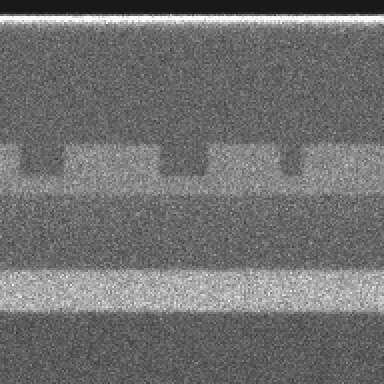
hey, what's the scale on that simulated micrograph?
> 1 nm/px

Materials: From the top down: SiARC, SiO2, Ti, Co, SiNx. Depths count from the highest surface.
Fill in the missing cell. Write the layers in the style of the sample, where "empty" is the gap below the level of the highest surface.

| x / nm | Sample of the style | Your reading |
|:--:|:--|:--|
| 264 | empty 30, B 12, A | SiARC 128, SiO2 50, Ti 76, Co 42, SiNx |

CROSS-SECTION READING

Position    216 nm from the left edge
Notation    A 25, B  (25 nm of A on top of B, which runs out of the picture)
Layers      SiARC 128, SiO2 50, Ti 76, Co 42, SiNx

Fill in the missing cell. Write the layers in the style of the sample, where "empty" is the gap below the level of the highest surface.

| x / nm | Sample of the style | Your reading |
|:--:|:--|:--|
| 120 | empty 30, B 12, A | SiARC 128, SiO2 50, Ti 76, Co 42, SiNx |